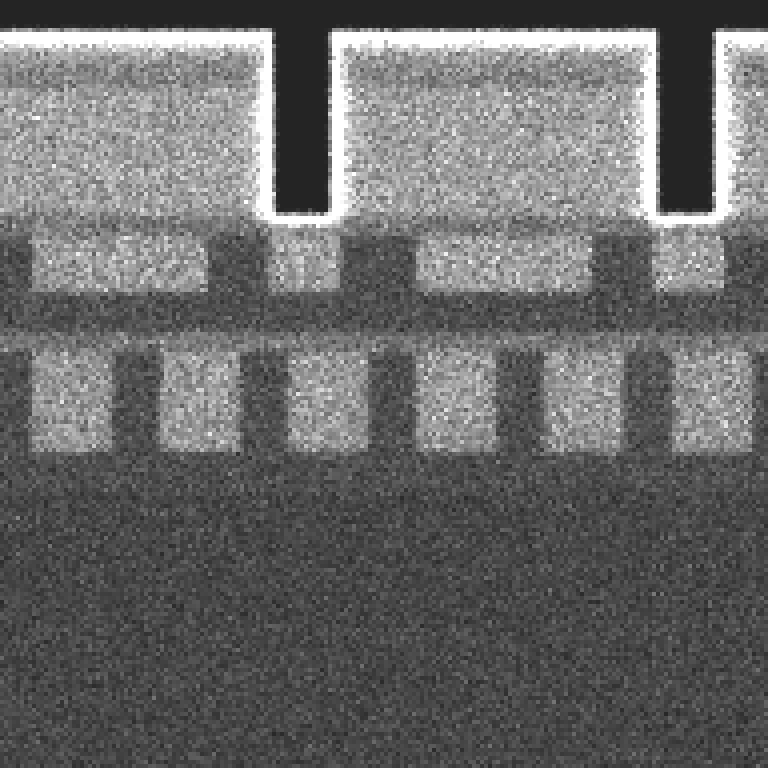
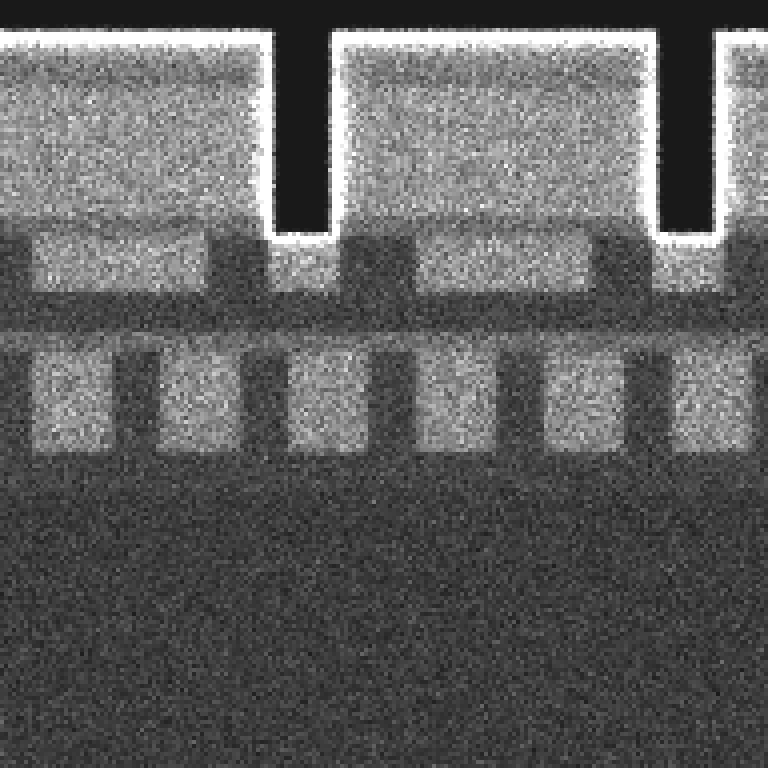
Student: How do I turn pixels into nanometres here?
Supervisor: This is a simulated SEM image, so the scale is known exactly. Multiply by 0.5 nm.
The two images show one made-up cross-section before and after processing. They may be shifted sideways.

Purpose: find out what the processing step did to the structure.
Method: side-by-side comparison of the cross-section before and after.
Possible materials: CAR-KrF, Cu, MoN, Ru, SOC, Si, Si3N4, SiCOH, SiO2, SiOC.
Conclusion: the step removed Si3N4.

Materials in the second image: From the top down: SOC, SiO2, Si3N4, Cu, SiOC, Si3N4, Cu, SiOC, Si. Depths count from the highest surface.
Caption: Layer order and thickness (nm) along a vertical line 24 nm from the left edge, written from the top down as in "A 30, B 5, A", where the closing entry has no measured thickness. SOC 28, SiO2 64, Si3N4 10, Cu 28, SiOC 20, Si3N4 10, Cu 50, SiOC 20, Si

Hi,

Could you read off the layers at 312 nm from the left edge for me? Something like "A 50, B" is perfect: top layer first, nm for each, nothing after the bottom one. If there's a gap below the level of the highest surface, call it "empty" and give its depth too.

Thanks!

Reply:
SOC 28, SiO2 64, Si3N4 10, SiOC 48, Si3N4 10, SiOC 70, Si